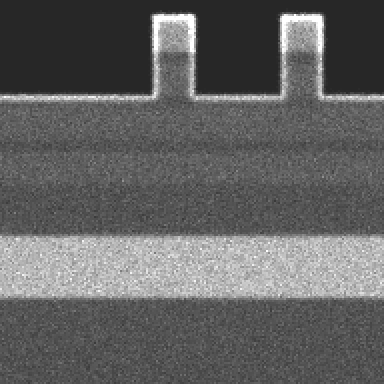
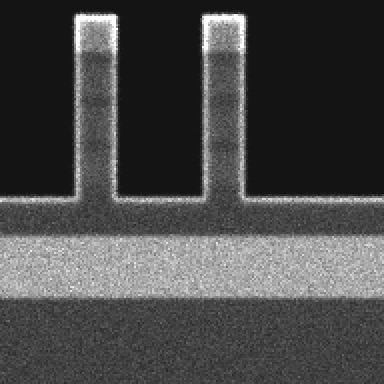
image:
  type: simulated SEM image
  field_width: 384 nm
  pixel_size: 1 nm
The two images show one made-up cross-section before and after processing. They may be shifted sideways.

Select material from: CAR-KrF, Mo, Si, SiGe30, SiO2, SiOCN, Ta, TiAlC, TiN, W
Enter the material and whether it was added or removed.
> Si and SiGe30 / removed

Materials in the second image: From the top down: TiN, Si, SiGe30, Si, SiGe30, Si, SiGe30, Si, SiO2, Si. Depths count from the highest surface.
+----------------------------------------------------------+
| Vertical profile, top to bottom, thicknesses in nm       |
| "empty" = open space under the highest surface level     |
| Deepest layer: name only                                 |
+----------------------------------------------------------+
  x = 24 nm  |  empty 182, Si 38, SiO2 62, Si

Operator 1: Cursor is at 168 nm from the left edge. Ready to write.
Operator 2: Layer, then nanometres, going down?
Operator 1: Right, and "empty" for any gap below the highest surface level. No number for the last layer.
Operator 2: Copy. empty 182, Si 38, SiO2 62, Si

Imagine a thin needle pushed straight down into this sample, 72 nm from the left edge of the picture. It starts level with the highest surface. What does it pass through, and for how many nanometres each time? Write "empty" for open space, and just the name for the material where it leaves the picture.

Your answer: empty 182, Si 38, SiO2 62, Si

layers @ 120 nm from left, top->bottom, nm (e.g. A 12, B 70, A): empty 182, Si 38, SiO2 62, Si